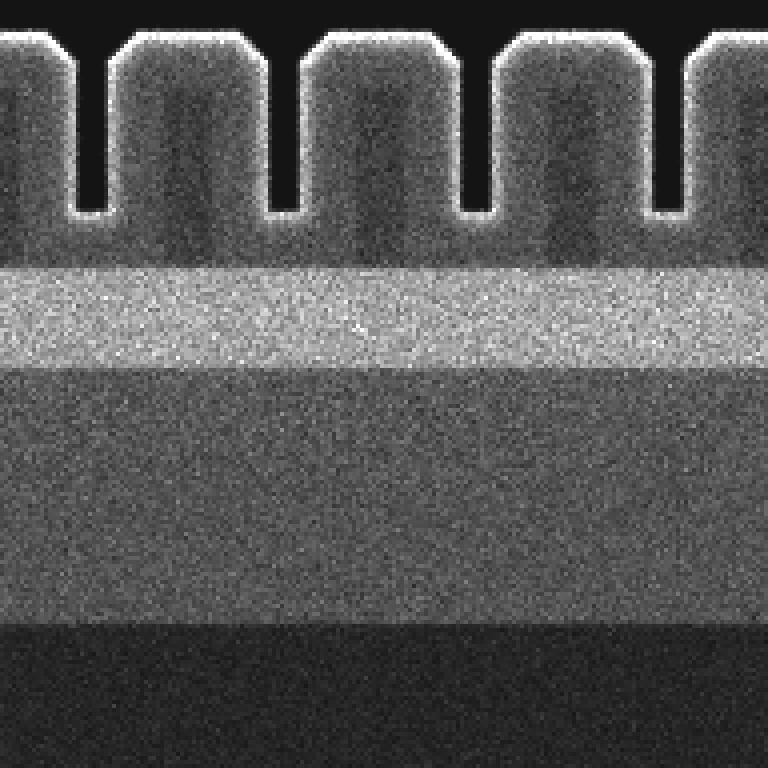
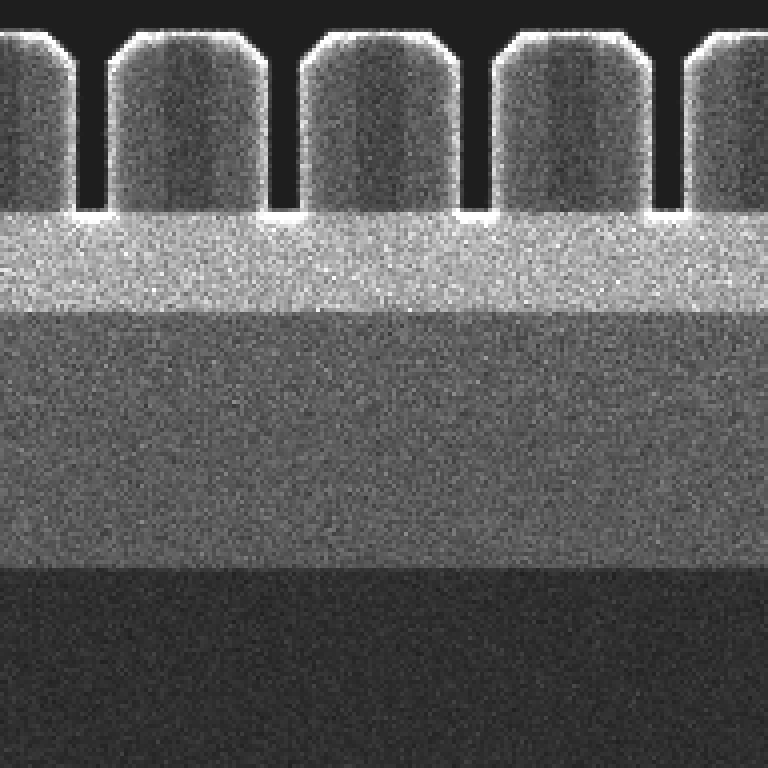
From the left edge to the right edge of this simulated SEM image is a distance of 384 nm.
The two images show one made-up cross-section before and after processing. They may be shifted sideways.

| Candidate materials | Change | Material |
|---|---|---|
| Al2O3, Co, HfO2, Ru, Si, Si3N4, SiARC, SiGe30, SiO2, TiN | removed | SiO2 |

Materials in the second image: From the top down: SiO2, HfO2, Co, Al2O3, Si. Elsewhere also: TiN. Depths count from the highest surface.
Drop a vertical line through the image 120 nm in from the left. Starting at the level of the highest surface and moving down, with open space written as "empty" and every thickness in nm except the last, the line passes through empty 2, SiO2 88, HfO2 50, Co 54, Al2O3 74, Si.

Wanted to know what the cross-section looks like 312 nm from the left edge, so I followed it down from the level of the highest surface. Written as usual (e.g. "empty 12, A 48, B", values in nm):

empty 2, SiO2 88, HfO2 50, Co 54, Al2O3 74, Si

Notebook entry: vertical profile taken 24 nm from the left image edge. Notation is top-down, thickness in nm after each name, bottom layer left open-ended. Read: empty 2, SiO2 88, HfO2 50, Co 54, Al2O3 74, Si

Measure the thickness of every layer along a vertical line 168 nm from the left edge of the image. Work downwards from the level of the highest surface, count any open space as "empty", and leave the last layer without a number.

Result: SiO2 90, HfO2 50, Co 54, Al2O3 74, Si